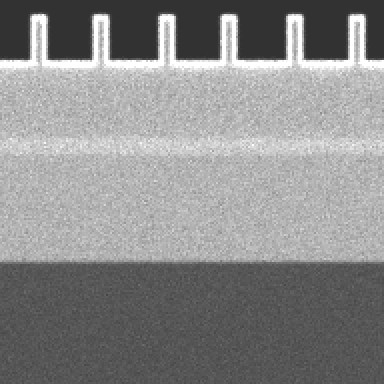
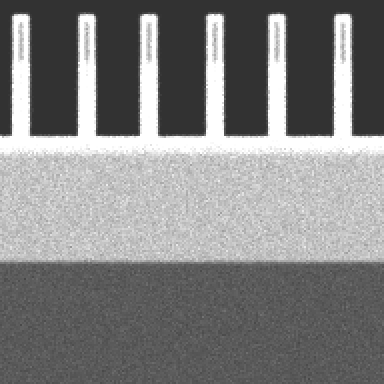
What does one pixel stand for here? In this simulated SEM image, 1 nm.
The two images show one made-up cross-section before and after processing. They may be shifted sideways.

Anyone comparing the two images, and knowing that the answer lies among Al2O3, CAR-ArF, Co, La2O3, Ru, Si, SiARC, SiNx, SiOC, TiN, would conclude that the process removed Co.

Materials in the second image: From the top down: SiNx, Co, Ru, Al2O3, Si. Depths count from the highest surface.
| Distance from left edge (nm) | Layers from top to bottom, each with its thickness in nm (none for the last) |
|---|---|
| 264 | empty 122, Ru 16, Al2O3 108, Si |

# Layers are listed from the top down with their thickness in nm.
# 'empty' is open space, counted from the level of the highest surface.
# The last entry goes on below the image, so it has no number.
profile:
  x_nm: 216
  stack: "SiNx 46, Co 76, Ru 16, Al2O3 108, Si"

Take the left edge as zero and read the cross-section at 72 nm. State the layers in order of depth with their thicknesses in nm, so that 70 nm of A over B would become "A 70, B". empty 122, Ru 16, Al2O3 108, Si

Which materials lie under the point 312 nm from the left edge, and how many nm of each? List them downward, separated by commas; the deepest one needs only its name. empty 122, Ru 16, Al2O3 108, Si